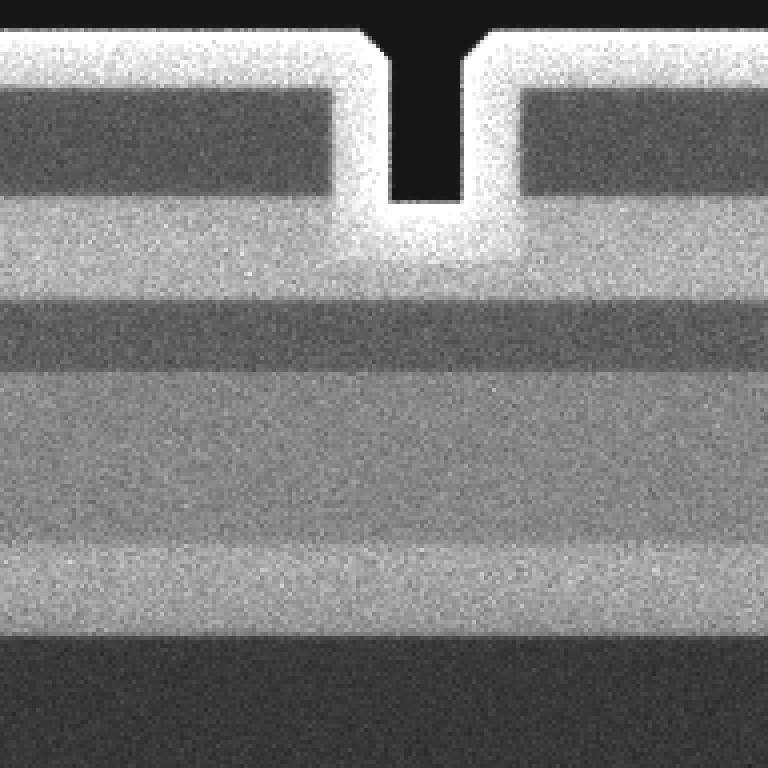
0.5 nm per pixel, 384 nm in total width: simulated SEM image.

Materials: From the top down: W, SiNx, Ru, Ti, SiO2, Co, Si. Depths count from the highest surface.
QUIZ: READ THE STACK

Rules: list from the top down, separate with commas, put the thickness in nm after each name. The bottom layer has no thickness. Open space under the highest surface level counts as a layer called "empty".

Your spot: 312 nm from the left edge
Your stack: W 28, SiNx 54, Ru 52, Ti 36, SiO2 86, Co 46, Si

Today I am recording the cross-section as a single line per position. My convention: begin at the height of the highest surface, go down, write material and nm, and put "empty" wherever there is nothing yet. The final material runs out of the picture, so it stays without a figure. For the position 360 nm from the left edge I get W 28, SiNx 54, Ru 52, Ti 36, SiO2 86, Co 46, Si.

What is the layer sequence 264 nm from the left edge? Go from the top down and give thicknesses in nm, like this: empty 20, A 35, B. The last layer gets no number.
W 28, SiNx 54, Ru 52, Ti 36, SiO2 86, Co 46, Si